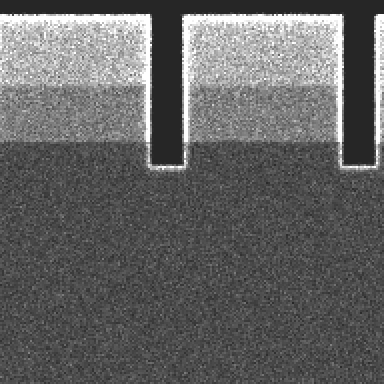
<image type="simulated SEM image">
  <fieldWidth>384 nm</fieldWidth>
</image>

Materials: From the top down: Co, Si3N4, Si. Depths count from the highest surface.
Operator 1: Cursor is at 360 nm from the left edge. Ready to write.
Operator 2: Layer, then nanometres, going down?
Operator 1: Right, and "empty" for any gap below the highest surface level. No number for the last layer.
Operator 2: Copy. empty 150, Si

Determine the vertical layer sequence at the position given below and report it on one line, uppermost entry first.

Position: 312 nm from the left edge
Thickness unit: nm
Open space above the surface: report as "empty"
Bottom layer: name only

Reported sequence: Co 70, Si3N4 56, Si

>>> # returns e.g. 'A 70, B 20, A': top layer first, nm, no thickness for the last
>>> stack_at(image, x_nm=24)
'Co 70, Si3N4 56, Si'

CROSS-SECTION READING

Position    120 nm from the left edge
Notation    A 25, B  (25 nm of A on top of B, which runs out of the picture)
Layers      Co 70, Si3N4 56, Si